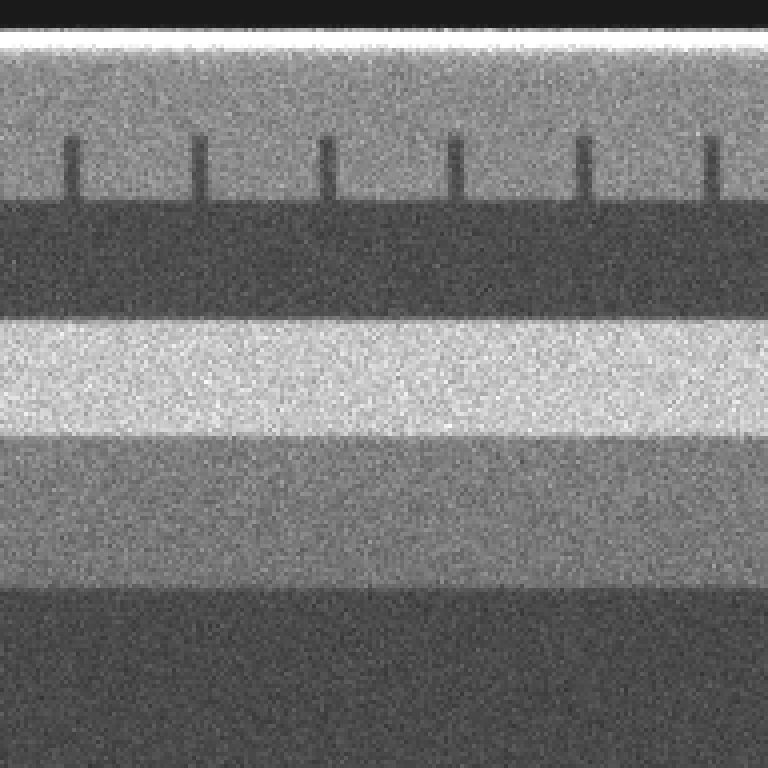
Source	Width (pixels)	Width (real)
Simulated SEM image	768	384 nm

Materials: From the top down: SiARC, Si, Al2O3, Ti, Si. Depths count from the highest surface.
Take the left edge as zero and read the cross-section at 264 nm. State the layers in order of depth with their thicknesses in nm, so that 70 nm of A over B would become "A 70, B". SiARC 84, Si 60, Al2O3 58, Ti 76, Si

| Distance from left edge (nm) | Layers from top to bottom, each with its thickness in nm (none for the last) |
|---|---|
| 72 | SiARC 84, Si 60, Al2O3 58, Ti 76, Si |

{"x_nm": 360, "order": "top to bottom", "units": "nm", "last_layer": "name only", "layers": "SiARC 84, Si 60, Al2O3 58, Ti 76, Si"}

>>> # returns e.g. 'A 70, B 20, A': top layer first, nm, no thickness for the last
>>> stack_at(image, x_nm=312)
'SiARC 84, Si 60, Al2O3 58, Ti 76, Si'